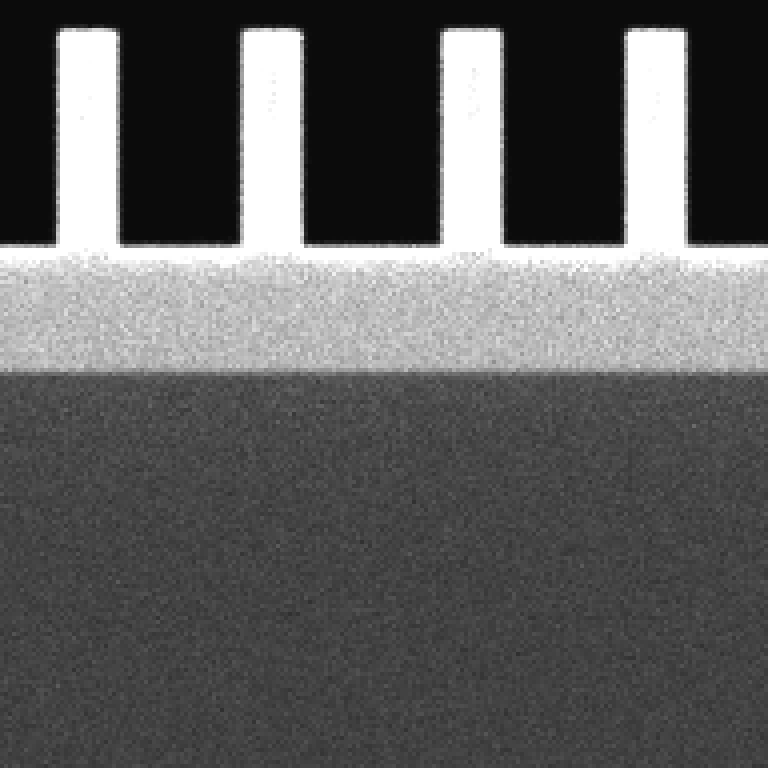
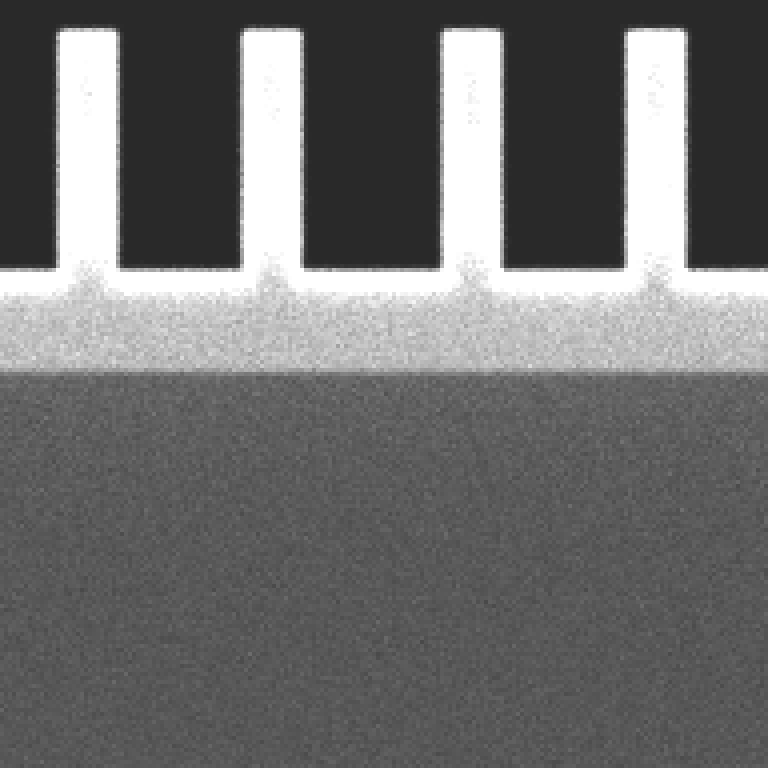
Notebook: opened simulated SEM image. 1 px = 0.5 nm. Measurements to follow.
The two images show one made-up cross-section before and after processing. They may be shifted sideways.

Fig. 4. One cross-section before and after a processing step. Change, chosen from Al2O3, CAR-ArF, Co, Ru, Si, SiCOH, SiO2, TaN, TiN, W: TiN removed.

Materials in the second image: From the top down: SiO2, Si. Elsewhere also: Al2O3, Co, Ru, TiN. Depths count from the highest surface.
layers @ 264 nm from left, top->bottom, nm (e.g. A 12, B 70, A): empty 120, SiO2 50, Si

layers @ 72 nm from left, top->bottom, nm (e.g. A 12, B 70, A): empty 120, SiO2 50, Si